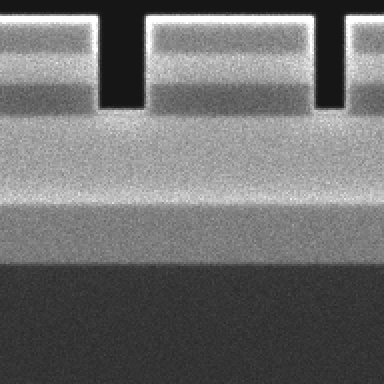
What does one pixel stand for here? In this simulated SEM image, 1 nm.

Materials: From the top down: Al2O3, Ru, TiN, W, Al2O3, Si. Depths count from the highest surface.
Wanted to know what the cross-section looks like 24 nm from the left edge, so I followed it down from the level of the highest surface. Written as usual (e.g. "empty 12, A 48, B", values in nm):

Al2O3 38, Ru 30, TiN 32, W 88, Al2O3 60, Si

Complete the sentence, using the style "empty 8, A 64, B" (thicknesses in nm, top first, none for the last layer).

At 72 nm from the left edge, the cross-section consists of Al2O3 38, Ru 30, TiN 32, W 88, Al2O3 60, Si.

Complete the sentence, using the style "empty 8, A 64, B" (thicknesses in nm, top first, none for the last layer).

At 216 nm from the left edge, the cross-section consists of Al2O3 38, Ru 30, TiN 32, W 88, Al2O3 60, Si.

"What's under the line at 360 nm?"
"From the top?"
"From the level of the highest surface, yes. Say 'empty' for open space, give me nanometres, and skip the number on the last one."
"Al2O3 38, Ru 30, TiN 32, W 88, Al2O3 60, Si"